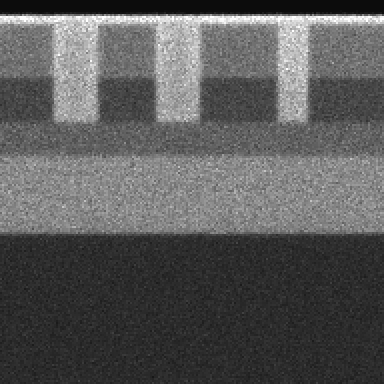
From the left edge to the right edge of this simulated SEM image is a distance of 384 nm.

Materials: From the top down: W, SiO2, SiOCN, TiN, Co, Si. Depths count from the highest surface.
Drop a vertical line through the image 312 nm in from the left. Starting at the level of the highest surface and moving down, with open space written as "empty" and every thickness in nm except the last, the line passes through W 8, SiO2 54, SiOCN 44, TiN 34, Co 78, Si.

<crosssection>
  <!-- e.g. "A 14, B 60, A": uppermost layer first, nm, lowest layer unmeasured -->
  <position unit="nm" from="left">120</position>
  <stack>W 8, SiO2 54, SiOCN 44, TiN 34, Co 78, Si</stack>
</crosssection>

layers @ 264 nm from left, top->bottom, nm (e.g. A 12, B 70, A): W 8, SiO2 54, SiOCN 44, TiN 34, Co 78, Si